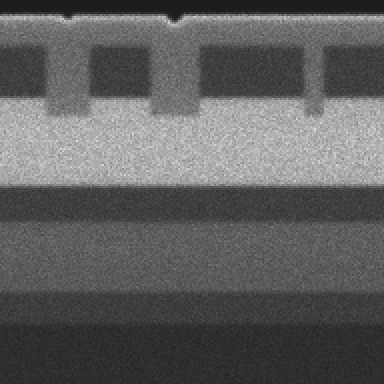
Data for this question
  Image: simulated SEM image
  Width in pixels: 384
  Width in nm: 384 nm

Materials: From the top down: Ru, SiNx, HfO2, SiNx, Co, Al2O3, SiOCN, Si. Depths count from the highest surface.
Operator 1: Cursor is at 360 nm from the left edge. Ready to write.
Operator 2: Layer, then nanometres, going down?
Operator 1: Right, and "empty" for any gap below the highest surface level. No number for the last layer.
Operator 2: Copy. Ru 30, SiNx 52, HfO2 88, SiNx 36, Co 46, Al2O3 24, SiOCN 32, Si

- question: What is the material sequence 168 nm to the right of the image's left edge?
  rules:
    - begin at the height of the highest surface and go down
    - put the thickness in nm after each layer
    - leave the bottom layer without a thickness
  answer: empty 4, Ru 96, HfO2 70, SiNx 36, Co 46, Al2O3 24, SiOCN 32, Si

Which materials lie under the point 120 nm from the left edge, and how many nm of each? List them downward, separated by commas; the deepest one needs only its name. Ru 30, SiNx 52, HfO2 88, SiNx 36, Co 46, Al2O3 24, SiOCN 32, Si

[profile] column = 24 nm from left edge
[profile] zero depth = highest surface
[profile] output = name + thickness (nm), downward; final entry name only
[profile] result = Ru 30, SiNx 52, HfO2 88, SiNx 36, Co 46, Al2O3 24, SiOCN 32, Si